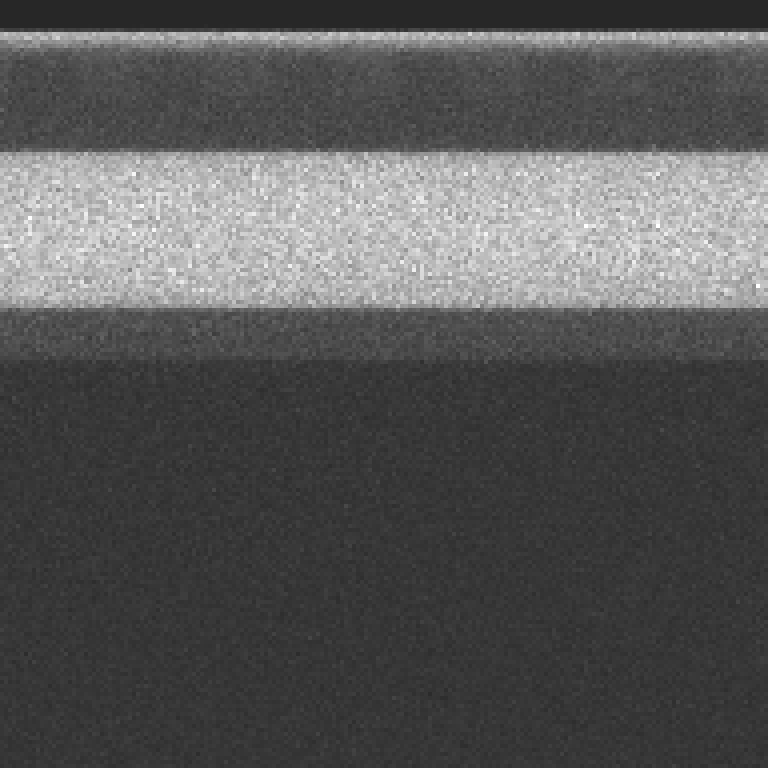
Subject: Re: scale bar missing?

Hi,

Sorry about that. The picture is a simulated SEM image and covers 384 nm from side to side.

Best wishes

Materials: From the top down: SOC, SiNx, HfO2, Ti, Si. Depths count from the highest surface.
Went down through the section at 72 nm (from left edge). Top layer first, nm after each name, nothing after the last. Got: SOC 6, SiNx 54, HfO2 78, Ti 26, Si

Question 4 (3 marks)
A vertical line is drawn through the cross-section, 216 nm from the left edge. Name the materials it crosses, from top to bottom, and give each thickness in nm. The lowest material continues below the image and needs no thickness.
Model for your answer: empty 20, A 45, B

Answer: SOC 6, SiNx 54, HfO2 78, Ti 26, Si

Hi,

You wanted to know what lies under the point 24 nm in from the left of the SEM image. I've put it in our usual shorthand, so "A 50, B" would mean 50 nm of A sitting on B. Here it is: SOC 6, SiNx 54, HfO2 78, Ti 26, Si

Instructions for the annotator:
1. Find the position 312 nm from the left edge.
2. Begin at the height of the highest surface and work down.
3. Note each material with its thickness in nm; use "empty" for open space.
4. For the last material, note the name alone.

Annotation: SOC 32, SiNx 28, HfO2 78, Ti 26, Si